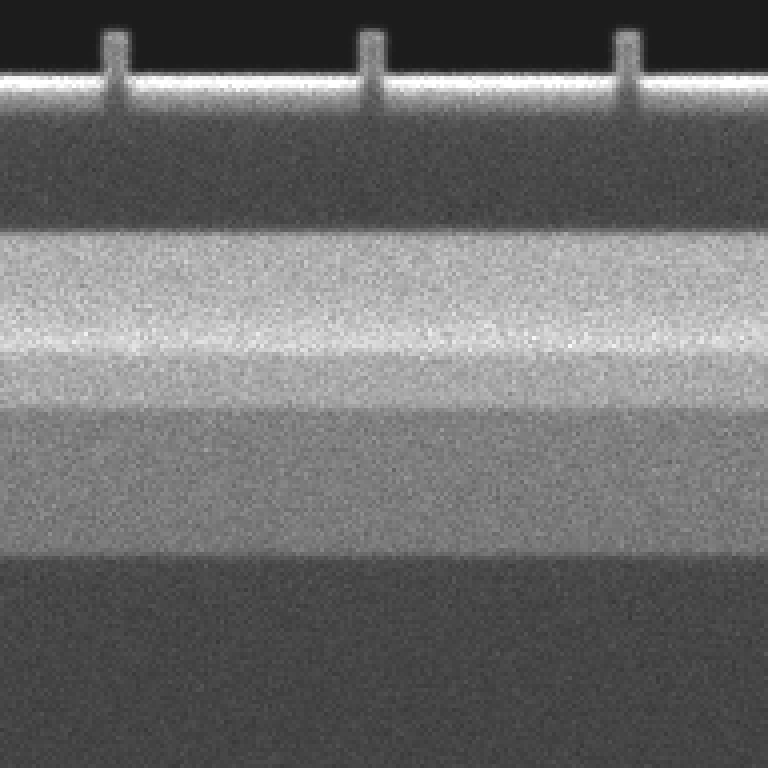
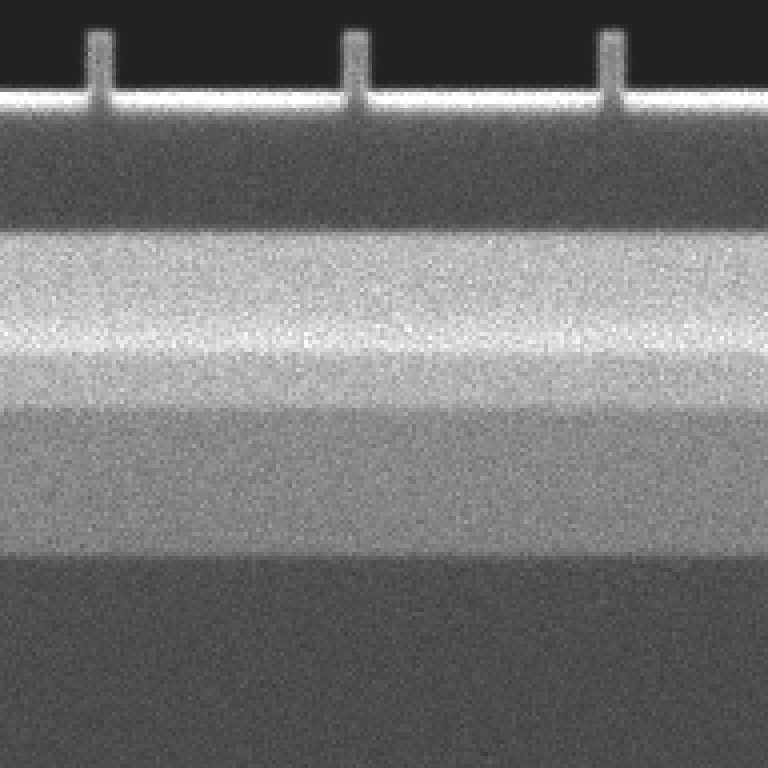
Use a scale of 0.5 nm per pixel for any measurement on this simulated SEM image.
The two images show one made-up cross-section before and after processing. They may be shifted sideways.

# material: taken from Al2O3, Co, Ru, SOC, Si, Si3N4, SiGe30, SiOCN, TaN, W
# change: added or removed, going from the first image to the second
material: SOC
change: removed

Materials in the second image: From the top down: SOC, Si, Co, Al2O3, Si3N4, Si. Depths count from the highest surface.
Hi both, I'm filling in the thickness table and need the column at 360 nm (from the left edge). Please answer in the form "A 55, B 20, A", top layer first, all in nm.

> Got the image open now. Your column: empty 30, SOC 10, Si 60, Co 60, Al2O3 28, Si3N4 74, Si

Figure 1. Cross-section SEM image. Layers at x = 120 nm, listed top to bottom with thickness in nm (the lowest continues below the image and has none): empty 30, SOC 10, Si 60, Co 60, Al2O3 28, Si3N4 74, Si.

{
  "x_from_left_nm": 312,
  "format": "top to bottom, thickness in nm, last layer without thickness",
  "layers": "empty 30, SOC 10, Si 60, Co 60, Al2O3 28, Si3N4 74, Si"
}